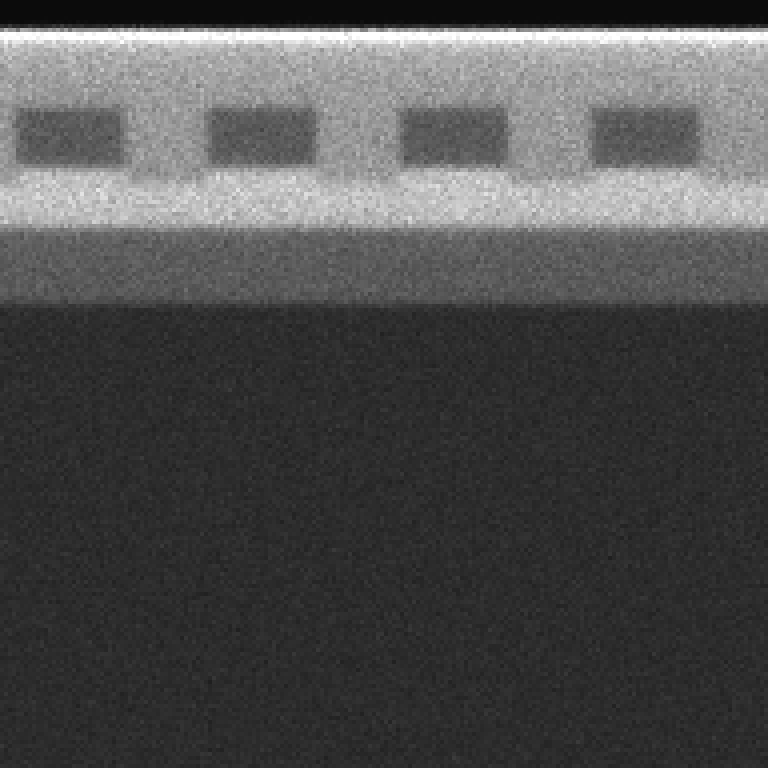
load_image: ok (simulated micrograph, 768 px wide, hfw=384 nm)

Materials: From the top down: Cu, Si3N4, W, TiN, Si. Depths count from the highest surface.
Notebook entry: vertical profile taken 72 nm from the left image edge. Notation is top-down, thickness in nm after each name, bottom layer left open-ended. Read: Cu 76, W 22, TiN 38, Si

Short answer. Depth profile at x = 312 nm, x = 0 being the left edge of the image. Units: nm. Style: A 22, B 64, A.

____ Cu 38, Si3N4 30, W 30, TiN 38, Si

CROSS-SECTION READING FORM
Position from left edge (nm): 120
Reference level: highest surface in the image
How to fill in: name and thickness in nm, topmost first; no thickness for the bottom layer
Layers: Cu 38, Si3N4 30, W 30, TiN 38, Si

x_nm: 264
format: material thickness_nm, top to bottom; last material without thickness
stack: Cu 76, W 22, TiN 38, Si